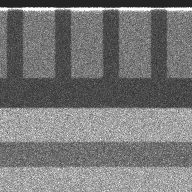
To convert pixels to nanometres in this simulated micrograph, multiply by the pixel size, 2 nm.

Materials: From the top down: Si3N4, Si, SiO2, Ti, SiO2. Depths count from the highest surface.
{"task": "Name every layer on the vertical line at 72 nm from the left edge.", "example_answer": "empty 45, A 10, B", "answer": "Si3N4 140, Si 60, SiO2 68, Ti 50, SiO2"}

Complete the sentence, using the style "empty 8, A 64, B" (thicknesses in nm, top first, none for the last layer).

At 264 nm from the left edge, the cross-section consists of Si3N4 140, Si 60, SiO2 68, Ti 50, SiO2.